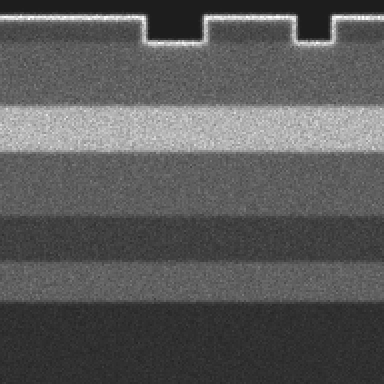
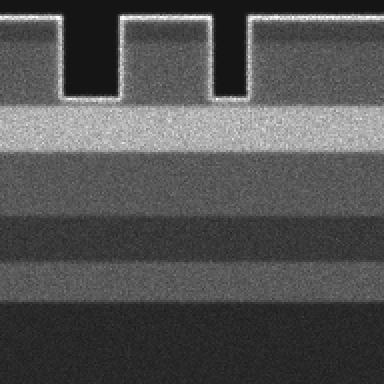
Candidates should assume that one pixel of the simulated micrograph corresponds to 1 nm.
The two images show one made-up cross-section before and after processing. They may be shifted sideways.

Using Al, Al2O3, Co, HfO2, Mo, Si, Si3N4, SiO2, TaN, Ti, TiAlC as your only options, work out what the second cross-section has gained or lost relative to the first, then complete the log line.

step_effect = removed Co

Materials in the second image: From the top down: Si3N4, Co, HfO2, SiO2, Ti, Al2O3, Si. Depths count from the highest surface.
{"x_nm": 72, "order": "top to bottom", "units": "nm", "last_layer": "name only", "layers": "empty 82, Co 8, HfO2 46, SiO2 64, Ti 46, Al2O3 40, Si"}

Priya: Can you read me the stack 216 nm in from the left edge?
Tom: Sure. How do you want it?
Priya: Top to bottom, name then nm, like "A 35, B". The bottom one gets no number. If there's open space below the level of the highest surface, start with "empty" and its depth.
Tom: empty 82, Co 8, HfO2 46, SiO2 64, Ti 46, Al2O3 40, Si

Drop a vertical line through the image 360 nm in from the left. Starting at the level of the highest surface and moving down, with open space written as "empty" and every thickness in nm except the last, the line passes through Si3N4 26, Co 64, HfO2 46, SiO2 64, Ti 46, Al2O3 40, Si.